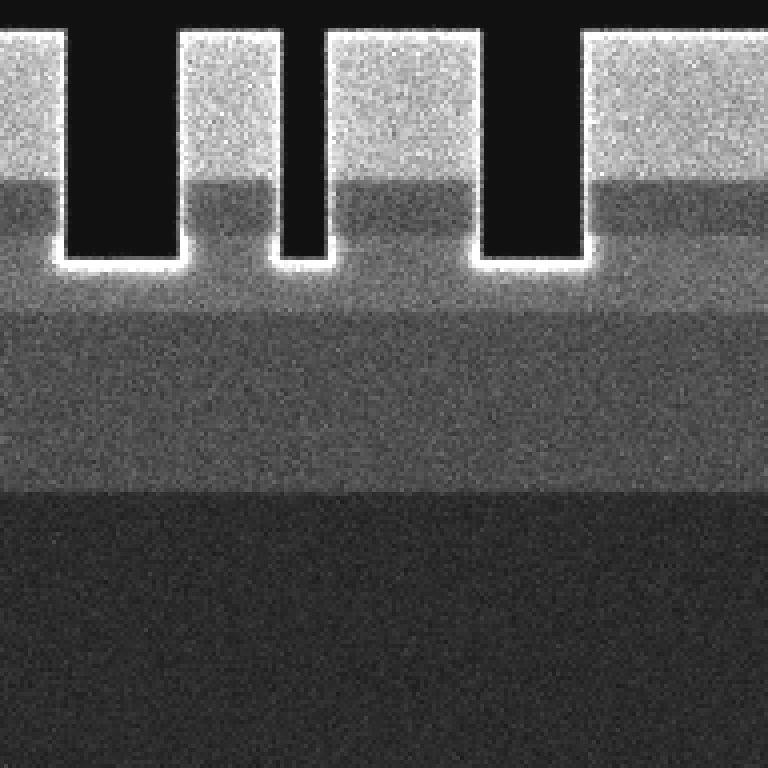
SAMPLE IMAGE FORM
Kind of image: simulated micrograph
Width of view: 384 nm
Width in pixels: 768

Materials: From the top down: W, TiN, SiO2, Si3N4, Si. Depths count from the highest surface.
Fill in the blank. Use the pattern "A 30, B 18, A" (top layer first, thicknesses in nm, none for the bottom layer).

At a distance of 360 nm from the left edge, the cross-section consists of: W 74, TiN 28, SiO2 38, Si3N4 90, Si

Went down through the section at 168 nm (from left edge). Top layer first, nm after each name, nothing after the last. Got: W 74, TiN 28, SiO2 38, Si3N4 90, Si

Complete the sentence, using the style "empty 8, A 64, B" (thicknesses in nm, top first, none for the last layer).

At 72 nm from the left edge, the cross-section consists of empty 114, SiO2 26, Si3N4 90, Si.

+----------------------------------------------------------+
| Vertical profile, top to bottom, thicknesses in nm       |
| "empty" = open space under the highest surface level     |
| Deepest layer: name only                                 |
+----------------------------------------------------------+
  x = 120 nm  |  W 74, TiN 28, SiO2 38, Si3N4 90, Si